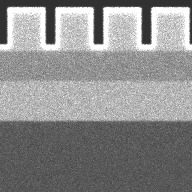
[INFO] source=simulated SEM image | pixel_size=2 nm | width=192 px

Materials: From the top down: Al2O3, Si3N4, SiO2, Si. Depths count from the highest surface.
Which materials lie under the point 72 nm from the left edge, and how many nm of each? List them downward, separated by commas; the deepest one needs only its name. Al2O3 86, Si3N4 60, SiO2 80, Si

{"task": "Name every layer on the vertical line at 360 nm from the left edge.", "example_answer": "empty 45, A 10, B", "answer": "Al2O3 86, Si3N4 60, SiO2 80, Si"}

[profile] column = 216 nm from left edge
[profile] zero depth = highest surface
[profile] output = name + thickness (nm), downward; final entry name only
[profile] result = Al2O3 86, Si3N4 60, SiO2 80, Si